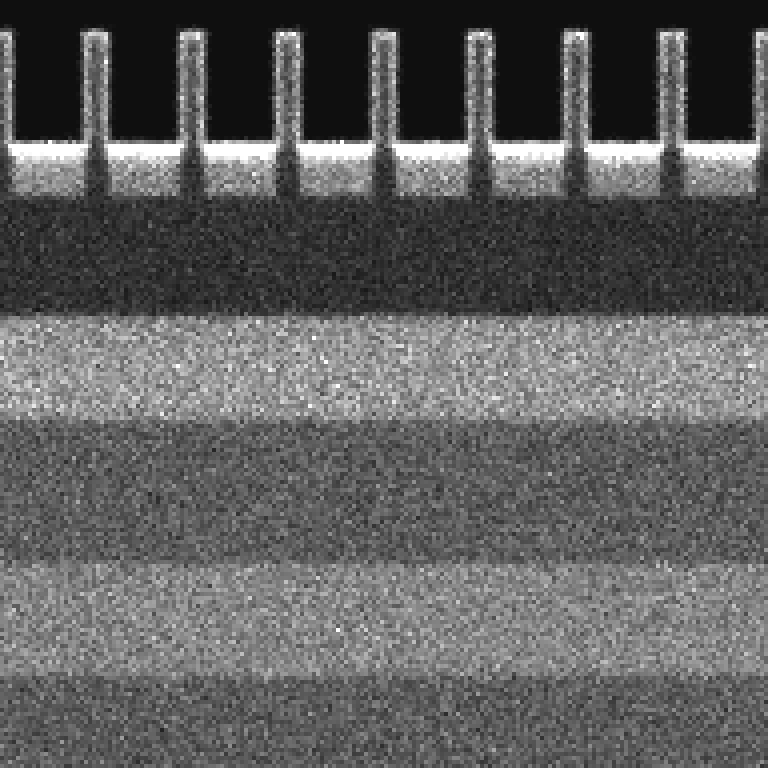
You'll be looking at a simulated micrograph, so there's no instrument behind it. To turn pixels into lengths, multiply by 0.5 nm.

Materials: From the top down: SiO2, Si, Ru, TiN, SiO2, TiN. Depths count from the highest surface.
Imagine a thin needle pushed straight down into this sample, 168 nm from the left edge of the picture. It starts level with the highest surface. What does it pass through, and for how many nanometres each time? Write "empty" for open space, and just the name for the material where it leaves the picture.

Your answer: empty 56, SiO2 26, Si 60, Ru 52, TiN 72, SiO2 56, TiN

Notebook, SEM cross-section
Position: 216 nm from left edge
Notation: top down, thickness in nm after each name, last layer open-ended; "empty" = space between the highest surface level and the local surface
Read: empty 56, SiO2 26, Si 60, Ru 52, TiN 72, SiO2 56, TiN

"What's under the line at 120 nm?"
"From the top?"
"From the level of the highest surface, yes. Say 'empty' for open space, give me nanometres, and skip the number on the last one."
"empty 56, SiO2 26, Si 60, Ru 52, TiN 72, SiO2 56, TiN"